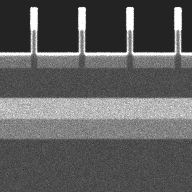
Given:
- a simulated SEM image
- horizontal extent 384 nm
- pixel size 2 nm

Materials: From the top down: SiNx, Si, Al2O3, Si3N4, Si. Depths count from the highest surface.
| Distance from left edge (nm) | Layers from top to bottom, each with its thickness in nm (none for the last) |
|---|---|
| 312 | empty 90, SiNx 30, Si 60, Al2O3 42, Si3N4 40, Si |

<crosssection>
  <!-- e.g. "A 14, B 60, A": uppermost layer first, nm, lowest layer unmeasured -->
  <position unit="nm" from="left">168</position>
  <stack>Si 180, Al2O3 42, Si3N4 40, Si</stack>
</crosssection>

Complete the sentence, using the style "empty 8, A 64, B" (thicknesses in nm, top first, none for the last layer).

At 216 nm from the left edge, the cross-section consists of empty 90, SiNx 30, Si 60, Al2O3 42, Si3N4 40, Si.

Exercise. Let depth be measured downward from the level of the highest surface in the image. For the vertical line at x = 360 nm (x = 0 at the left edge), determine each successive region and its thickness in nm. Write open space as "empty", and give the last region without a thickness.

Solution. Si 180, Al2O3 42, Si3N4 40, Si